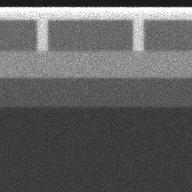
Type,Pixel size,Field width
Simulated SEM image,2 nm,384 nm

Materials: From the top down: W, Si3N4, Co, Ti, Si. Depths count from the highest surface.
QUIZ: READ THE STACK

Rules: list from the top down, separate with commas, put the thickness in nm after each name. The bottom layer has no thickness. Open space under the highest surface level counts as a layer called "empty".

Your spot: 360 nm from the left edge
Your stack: W 24, Si3N4 62, Co 54, Ti 58, Si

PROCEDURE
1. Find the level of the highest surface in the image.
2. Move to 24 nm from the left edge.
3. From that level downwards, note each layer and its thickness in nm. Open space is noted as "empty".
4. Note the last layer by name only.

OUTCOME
W 24, Si3N4 62, Co 54, Ti 58, Si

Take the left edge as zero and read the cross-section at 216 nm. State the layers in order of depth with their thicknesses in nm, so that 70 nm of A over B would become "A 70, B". W 24, Si3N4 62, Co 54, Ti 58, Si